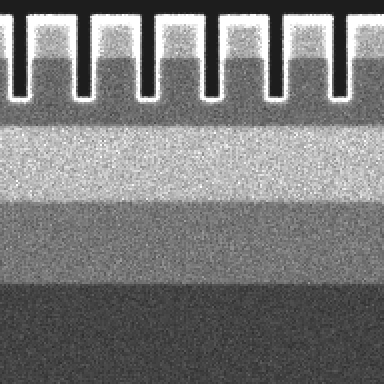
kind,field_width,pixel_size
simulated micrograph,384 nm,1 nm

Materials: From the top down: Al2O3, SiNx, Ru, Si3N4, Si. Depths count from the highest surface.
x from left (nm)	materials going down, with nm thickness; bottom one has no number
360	Al2O3 42, SiNx 68, Ru 76, Si3N4 82, Si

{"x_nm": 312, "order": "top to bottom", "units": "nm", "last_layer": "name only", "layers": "Al2O3 42, SiNx 68, Ru 76, Si3N4 82, Si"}